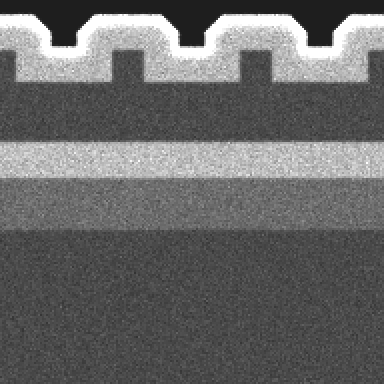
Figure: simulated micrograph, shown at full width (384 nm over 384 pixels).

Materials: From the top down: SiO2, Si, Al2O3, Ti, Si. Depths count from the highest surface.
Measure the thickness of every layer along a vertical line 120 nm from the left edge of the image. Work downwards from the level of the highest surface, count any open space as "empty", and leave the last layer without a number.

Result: SiO2 34, Si 92, Al2O3 36, Ti 52, Si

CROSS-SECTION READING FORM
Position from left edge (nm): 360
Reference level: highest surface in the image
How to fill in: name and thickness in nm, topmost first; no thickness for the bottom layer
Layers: SiO2 66, Si 60, Al2O3 36, Ti 52, Si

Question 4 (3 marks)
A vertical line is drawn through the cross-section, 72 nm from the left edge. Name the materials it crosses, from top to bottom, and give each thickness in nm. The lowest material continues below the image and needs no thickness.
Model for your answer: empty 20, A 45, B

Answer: empty 32, SiO2 34, Si 60, Al2O3 36, Ti 52, Si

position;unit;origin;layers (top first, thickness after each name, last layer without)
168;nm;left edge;empty 8, SiO2 58, Si 60, Al2O3 36, Ti 52, Si